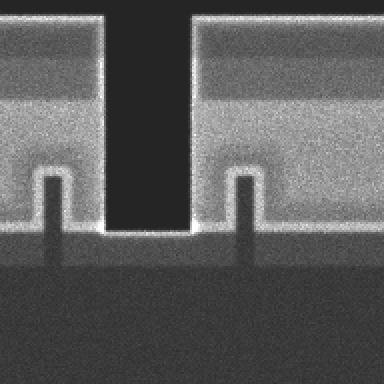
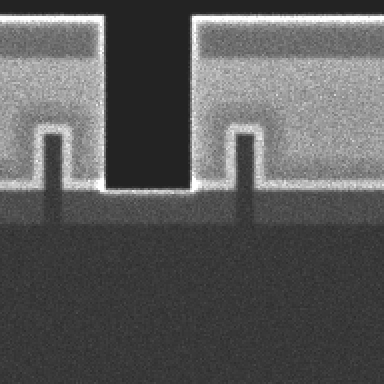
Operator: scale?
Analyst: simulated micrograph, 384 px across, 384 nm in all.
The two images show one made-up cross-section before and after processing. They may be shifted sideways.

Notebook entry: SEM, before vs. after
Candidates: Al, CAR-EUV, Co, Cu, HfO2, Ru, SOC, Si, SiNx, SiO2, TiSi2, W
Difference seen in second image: SOC removed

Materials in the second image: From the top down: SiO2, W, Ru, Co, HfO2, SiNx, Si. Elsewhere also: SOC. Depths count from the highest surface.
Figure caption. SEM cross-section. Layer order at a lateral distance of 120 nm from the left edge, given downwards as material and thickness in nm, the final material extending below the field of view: empty 174, SiNx 34, Si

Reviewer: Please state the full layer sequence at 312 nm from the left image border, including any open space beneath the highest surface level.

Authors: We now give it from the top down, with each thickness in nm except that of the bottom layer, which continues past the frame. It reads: SiO2 42, W 100, Ru 10, Co 12, HfO2 10, SiNx 34, Si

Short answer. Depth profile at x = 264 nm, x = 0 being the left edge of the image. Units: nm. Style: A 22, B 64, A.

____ SiO2 42, W 44, Ru 10, Co 68, HfO2 10, SiNx 34, Si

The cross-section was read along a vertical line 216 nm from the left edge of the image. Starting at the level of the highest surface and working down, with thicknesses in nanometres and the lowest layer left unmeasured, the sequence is SiO2 42, W 46, Ru 16, Co 60, HfO2 10, SiNx 34, Si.